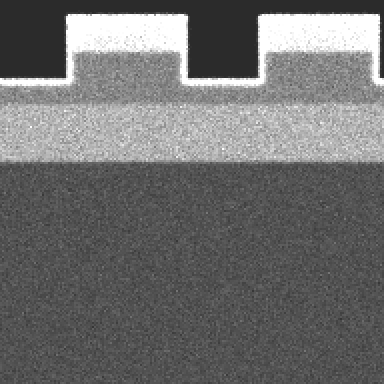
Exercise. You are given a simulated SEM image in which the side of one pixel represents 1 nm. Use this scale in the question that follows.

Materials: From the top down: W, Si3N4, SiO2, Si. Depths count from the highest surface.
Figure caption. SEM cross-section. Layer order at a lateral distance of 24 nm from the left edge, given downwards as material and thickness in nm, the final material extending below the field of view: empty 64, Si3N4 24, SiO2 58, Si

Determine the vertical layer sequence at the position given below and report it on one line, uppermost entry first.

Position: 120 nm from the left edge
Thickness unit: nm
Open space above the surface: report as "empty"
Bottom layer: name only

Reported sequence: W 36, Si3N4 52, SiO2 58, Si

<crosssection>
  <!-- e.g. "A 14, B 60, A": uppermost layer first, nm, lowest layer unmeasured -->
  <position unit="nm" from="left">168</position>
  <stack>W 36, Si3N4 52, SiO2 58, Si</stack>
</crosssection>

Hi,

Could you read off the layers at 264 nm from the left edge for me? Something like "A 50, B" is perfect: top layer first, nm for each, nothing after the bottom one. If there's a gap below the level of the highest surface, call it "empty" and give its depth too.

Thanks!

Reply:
W 36, Si3N4 52, SiO2 58, Si